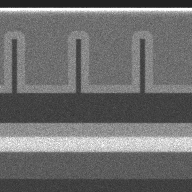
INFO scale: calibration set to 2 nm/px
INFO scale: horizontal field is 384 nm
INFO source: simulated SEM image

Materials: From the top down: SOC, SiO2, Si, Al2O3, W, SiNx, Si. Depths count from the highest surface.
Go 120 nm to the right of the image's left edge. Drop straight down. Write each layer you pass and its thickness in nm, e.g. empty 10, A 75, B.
SOC 154, SiO2 16, Si 60, Al2O3 28, W 30, SiNx 54, Si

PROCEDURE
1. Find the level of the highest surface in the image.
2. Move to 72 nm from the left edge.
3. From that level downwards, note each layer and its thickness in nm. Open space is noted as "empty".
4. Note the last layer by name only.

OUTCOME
SOC 154, SiO2 16, Si 60, Al2O3 28, W 30, SiNx 54, Si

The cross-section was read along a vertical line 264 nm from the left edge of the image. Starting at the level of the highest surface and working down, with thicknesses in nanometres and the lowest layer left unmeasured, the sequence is SOC 54, SiO2 116, Si 60, Al2O3 28, W 30, SiNx 54, Si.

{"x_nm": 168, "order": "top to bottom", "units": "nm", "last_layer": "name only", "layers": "SOC 46, SiO2 124, Si 60, Al2O3 28, W 30, SiNx 54, Si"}